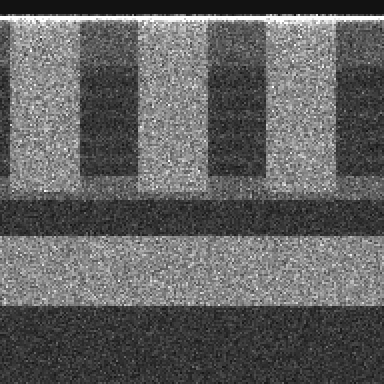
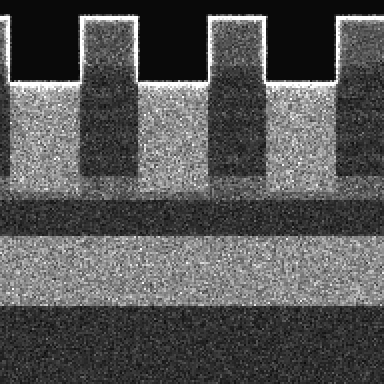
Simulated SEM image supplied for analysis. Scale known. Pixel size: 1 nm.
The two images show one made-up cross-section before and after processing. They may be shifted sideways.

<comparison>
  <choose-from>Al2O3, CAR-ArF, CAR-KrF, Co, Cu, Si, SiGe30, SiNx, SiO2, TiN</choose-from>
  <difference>Co removed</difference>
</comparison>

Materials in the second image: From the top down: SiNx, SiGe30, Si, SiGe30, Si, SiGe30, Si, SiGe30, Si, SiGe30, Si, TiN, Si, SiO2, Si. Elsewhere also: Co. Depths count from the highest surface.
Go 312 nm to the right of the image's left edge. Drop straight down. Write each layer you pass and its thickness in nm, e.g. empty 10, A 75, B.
empty 66, Co 110, TiN 8, Si 36, SiO2 70, Si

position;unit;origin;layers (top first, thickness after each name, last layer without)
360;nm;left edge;SiNx 50, SiGe30 10, Si 12, SiGe30 10, Si 12, SiGe30 10, Si 12, SiGe30 10, Si 12, SiGe30 10, Si 12, TiN 24, Si 36, SiO2 70, Si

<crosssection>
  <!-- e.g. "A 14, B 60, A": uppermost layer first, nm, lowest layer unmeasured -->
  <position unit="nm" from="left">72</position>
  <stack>empty 66, Co 110, TiN 8, Si 36, SiO2 70, Si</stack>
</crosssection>